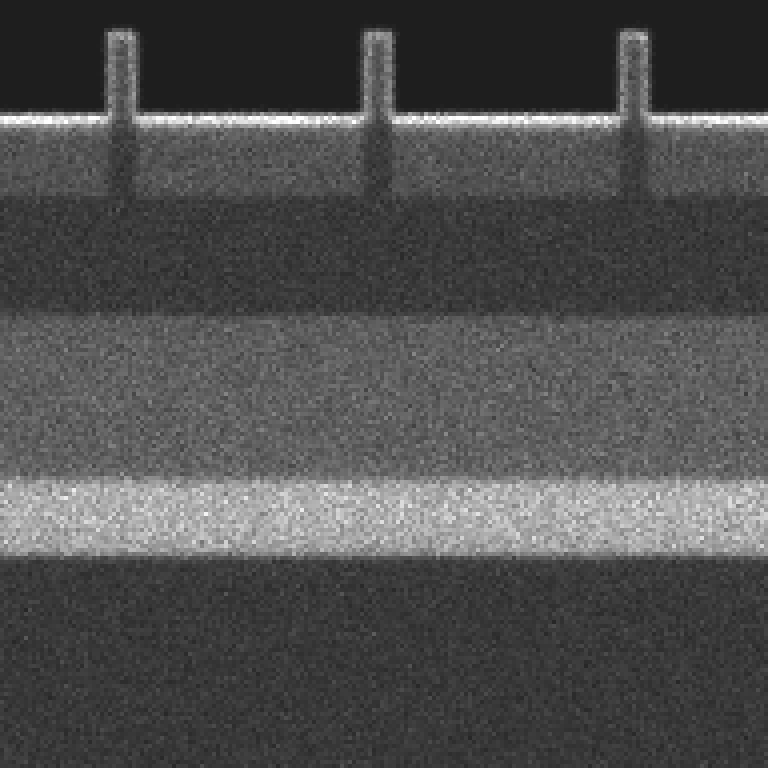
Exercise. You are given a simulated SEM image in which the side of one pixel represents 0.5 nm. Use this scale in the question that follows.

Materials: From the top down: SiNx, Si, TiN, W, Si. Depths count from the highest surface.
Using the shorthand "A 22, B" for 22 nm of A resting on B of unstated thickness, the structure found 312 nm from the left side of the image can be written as Si 142, TiN 82, W 38, Si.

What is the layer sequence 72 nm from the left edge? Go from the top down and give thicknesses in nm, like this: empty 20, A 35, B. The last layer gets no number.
empty 42, SiNx 40, Si 60, TiN 82, W 38, Si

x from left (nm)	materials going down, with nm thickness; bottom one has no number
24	empty 42, SiNx 40, Si 60, TiN 82, W 38, Si